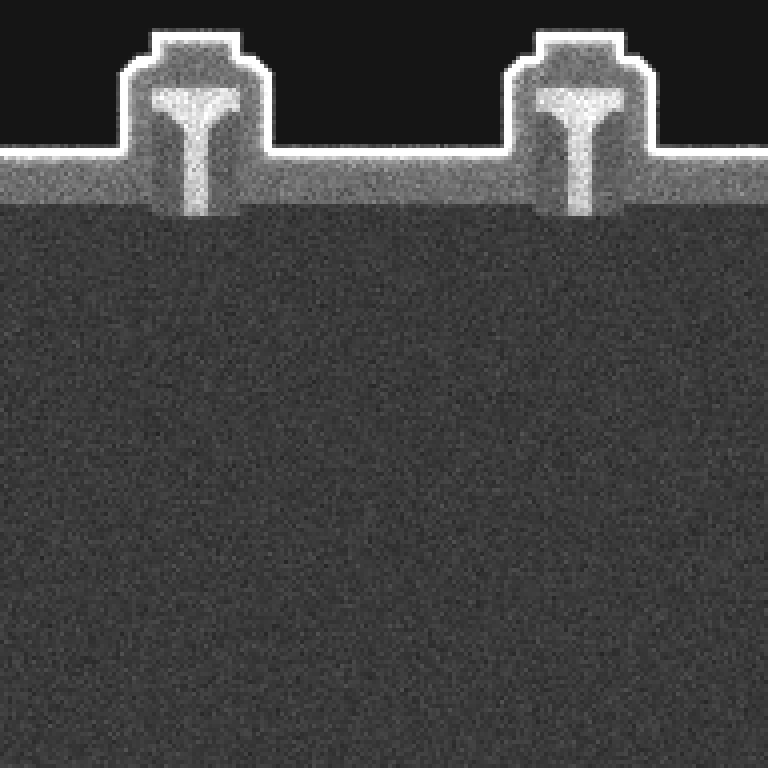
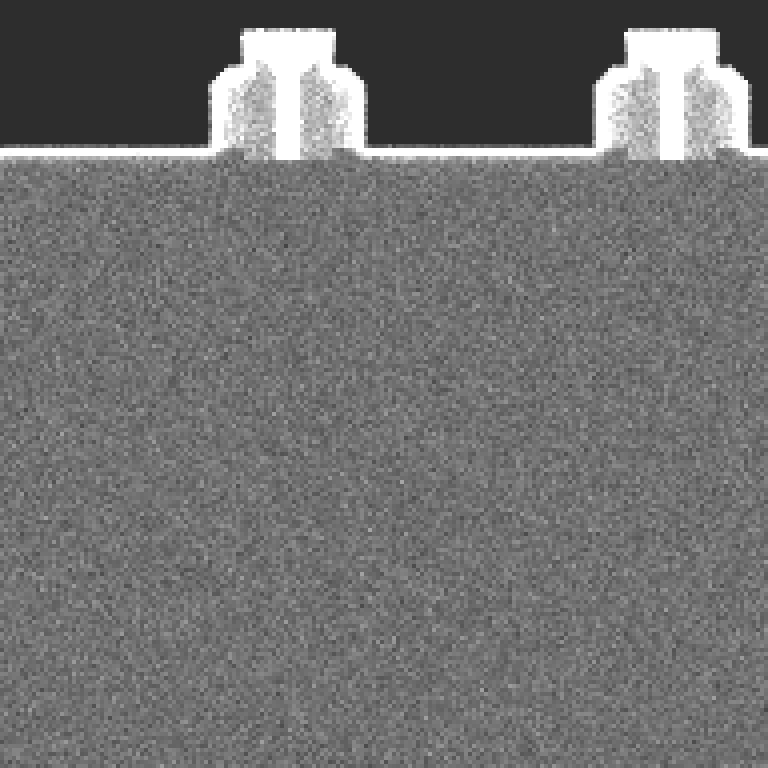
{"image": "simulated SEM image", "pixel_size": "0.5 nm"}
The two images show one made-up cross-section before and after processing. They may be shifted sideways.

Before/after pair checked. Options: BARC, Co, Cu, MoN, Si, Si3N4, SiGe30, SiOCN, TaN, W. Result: removed Si3N4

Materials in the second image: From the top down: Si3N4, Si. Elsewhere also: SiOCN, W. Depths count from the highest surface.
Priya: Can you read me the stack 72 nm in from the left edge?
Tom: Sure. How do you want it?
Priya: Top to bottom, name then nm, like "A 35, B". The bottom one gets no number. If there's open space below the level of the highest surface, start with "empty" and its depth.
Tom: empty 58, Si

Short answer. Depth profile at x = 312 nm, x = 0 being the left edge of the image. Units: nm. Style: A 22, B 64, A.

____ empty 18, Si3N4 40, Si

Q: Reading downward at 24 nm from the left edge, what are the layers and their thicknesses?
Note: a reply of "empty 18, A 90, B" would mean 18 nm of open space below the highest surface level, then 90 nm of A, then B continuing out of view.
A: empty 58, Si